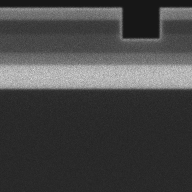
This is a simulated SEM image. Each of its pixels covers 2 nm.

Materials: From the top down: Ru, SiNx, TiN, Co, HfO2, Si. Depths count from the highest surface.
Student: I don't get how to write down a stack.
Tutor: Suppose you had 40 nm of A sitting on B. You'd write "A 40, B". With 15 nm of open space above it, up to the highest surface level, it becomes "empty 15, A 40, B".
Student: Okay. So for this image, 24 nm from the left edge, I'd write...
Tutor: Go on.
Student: Ru 24, SiNx 28, TiN 38, Co 24, HfO2 48, Si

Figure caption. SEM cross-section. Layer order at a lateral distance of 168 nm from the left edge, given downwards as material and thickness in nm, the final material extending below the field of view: Ru 24, SiNx 28, TiN 38, Co 24, HfO2 48, Si